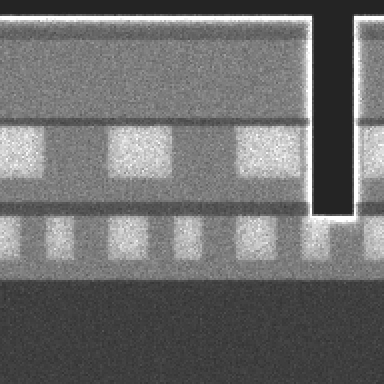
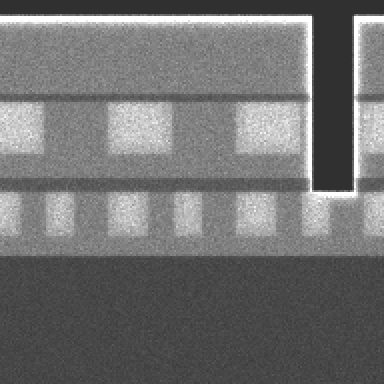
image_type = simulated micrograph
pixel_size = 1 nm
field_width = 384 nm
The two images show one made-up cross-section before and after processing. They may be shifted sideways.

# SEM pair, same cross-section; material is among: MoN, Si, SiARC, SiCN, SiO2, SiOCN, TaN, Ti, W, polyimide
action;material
removed;SiARC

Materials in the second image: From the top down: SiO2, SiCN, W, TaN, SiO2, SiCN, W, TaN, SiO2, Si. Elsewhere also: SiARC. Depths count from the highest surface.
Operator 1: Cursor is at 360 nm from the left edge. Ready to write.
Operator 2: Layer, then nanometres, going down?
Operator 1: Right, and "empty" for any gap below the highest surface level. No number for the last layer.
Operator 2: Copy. SiO2 78, SiCN 8, SiO2 76, SiCN 14, SiO2 64, Si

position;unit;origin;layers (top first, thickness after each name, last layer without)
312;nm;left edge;empty 176, W 34, TaN 10, SiO2 20, Si